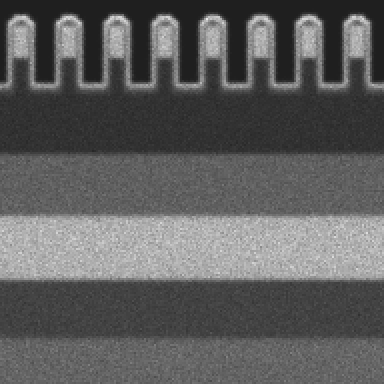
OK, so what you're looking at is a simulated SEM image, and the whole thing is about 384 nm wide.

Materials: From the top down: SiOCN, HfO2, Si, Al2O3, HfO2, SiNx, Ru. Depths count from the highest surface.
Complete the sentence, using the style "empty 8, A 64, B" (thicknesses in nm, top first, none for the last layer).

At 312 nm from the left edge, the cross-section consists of SiOCN 10, HfO2 32, Si 96, Al2O3 62, HfO2 64, SiNx 58, Ru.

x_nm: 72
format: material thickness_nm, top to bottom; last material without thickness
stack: SiOCN 10, HfO2 32, Si 96, Al2O3 62, HfO2 64, SiNx 58, Ru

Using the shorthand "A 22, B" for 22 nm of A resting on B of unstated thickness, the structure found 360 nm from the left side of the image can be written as SiOCN 10, HfO2 32, Si 96, Al2O3 62, HfO2 64, SiNx 58, Ru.